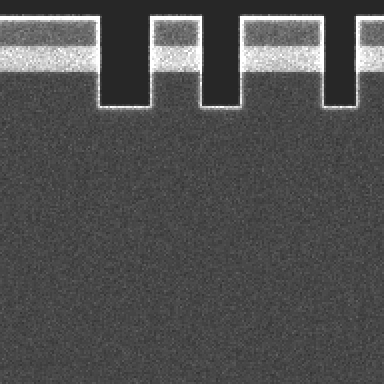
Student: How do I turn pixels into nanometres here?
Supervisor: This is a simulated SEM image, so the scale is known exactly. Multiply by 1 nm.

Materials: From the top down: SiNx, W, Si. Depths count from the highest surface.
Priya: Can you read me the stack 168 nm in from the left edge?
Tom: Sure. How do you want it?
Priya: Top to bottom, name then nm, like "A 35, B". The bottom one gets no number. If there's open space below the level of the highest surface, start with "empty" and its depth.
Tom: SiNx 30, W 26, Si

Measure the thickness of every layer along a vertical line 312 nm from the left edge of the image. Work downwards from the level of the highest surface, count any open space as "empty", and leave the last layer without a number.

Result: SiNx 30, W 26, Si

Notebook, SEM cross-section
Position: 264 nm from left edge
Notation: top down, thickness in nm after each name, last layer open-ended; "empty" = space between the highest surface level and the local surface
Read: SiNx 30, W 26, Si